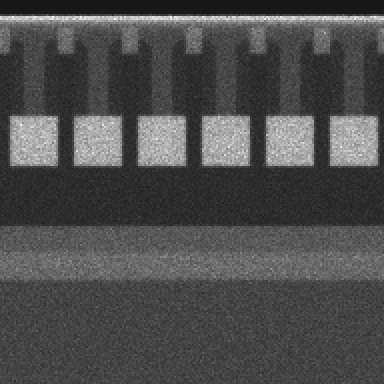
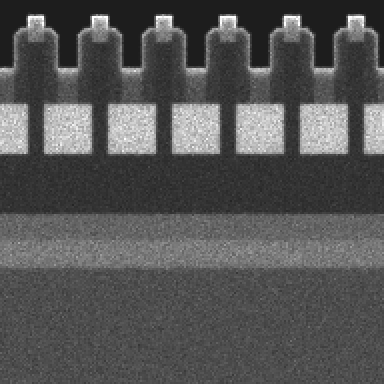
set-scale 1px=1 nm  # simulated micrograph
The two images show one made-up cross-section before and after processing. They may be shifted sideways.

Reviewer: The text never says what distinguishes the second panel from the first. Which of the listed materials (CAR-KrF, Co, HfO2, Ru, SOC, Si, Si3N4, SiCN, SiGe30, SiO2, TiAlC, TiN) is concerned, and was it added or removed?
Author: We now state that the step removed SOC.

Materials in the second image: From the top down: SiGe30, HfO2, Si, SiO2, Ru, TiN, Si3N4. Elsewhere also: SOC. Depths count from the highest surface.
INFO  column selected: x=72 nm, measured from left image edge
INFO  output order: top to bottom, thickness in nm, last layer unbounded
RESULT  empty 52, SOC 36, HfO2 50, Si 60, SiO2 26, Ru 28, TiN 36, Si3N4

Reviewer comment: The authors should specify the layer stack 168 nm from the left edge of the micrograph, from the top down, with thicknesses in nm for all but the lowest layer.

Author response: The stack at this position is Ru 26, Si 172, SiO2 26, Ru 28, TiN 36, Si3N4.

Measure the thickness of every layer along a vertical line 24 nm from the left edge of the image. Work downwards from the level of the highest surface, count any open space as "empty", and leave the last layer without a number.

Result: empty 12, SiGe30 76, HfO2 50, Si 60, SiO2 26, Ru 28, TiN 36, Si3N4